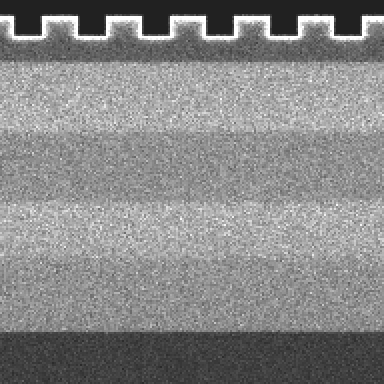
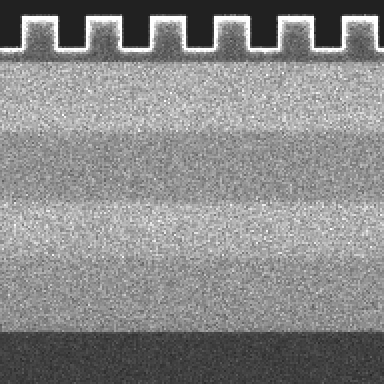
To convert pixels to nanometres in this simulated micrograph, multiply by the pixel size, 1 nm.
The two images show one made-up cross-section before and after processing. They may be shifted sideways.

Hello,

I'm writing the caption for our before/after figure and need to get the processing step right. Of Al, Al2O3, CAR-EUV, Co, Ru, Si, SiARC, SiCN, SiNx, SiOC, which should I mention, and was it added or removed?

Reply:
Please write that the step removed SiNx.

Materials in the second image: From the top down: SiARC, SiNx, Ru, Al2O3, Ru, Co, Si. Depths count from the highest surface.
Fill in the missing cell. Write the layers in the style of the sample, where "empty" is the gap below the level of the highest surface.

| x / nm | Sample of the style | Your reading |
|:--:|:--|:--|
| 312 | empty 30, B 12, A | SiARC 20, SiNx 26, Ru 70, Al2O3 70, Ru 56, Co 74, Si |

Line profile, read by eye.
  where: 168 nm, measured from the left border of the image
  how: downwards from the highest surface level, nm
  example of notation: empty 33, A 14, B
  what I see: SiARC 20, SiNx 26, Ru 70, Al2O3 70, Ru 56, Co 74, Si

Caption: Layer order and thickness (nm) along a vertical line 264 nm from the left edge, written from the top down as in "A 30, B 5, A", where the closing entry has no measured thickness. empty 32, SiNx 14, Ru 70, Al2O3 70, Ru 56, Co 74, Si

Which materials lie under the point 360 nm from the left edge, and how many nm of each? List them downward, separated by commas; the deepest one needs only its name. SiARC 20, SiNx 26, Ru 70, Al2O3 70, Ru 56, Co 74, Si